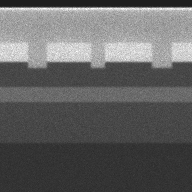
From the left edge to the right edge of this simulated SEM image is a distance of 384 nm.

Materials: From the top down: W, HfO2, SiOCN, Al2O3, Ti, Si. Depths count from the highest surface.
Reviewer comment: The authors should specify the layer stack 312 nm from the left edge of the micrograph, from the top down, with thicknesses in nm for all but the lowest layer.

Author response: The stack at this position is W 120, SiOCN 38, Al2O3 30, Ti 82, Si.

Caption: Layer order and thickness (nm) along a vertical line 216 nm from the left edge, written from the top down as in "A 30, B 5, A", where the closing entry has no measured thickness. W 70, HfO2 38, SiOCN 50, Al2O3 30, Ti 82, Si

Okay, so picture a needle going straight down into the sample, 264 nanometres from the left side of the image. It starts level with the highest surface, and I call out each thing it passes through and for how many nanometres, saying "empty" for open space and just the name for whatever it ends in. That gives W 70, HfO2 38, SiOCN 50, Al2O3 30, Ti 82, Si